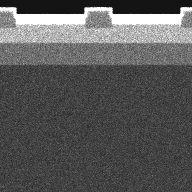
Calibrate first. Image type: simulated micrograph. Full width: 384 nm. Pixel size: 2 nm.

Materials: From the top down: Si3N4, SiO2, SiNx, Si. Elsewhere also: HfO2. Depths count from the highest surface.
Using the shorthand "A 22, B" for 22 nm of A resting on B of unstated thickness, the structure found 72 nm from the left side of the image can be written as empty 14, HfO2 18, SiO2 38, SiNx 44, Si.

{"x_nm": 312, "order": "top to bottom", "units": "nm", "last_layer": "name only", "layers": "empty 14, HfO2 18, SiO2 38, SiNx 44, Si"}